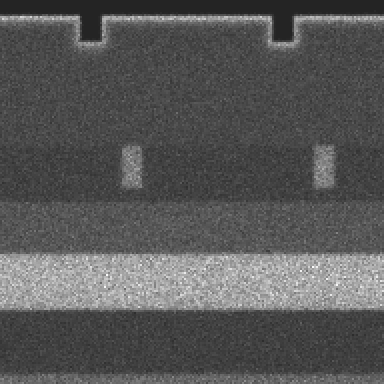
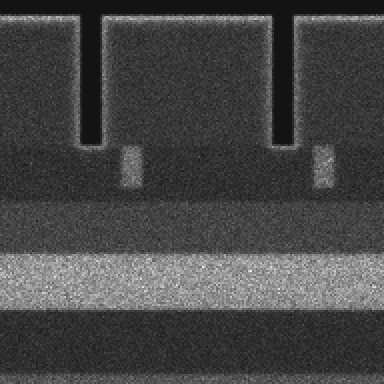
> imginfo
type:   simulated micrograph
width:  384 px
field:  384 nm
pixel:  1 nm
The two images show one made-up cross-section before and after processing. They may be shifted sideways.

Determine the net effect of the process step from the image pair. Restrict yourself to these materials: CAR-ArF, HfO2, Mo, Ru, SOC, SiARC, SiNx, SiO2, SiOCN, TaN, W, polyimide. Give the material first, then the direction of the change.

SOC: removed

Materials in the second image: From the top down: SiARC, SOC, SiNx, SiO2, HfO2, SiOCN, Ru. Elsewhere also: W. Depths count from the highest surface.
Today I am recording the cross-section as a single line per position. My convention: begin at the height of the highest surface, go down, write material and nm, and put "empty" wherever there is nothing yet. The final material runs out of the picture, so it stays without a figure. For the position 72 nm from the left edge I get SiARC 26, SOC 104, SiNx 56, SiO2 52, HfO2 56, SiOCN 64, Ru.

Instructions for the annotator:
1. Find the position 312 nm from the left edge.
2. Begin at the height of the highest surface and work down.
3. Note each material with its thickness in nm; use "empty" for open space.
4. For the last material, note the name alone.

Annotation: SiARC 26, SOC 104, SiNx 56, SiO2 52, HfO2 56, SiOCN 64, Ru